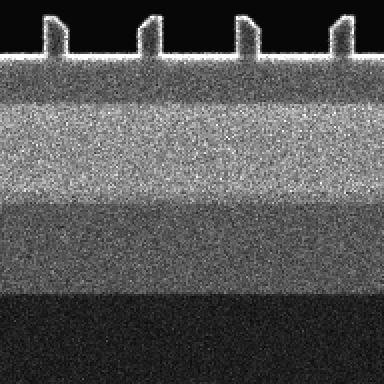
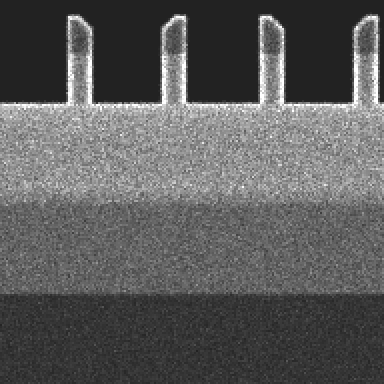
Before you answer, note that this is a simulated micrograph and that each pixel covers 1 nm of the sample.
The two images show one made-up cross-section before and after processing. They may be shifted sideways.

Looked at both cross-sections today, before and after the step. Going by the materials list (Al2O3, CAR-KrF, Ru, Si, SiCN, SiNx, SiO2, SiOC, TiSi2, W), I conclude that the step removed Al2O3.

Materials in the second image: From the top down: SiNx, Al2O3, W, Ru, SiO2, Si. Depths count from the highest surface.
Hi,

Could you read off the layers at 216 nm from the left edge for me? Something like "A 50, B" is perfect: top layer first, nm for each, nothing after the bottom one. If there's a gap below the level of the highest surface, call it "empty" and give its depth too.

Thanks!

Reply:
empty 88, W 88, Ru 12, SiO2 90, Si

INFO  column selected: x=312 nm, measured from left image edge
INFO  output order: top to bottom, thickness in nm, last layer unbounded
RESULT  empty 88, W 88, Ru 12, SiO2 90, Si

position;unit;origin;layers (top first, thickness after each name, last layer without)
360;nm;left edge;empty 6, SiNx 32, Al2O3 50, W 88, Ru 12, SiO2 90, Si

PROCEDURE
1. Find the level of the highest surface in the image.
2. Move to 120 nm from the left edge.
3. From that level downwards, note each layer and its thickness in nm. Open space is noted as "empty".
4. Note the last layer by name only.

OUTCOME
empty 88, W 88, Ru 12, SiO2 90, Si